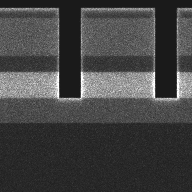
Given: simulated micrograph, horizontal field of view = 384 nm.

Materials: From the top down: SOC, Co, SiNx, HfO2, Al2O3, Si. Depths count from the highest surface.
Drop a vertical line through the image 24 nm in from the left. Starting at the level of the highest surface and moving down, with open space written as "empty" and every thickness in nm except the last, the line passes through SOC 20, Co 76, SiNx 32, HfO2 52, Al2O3 50, Si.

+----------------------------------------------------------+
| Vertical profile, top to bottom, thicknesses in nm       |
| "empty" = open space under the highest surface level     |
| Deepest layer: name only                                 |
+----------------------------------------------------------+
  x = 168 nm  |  SOC 20, Co 76, SiNx 32, HfO2 52, Al2O3 50, Si